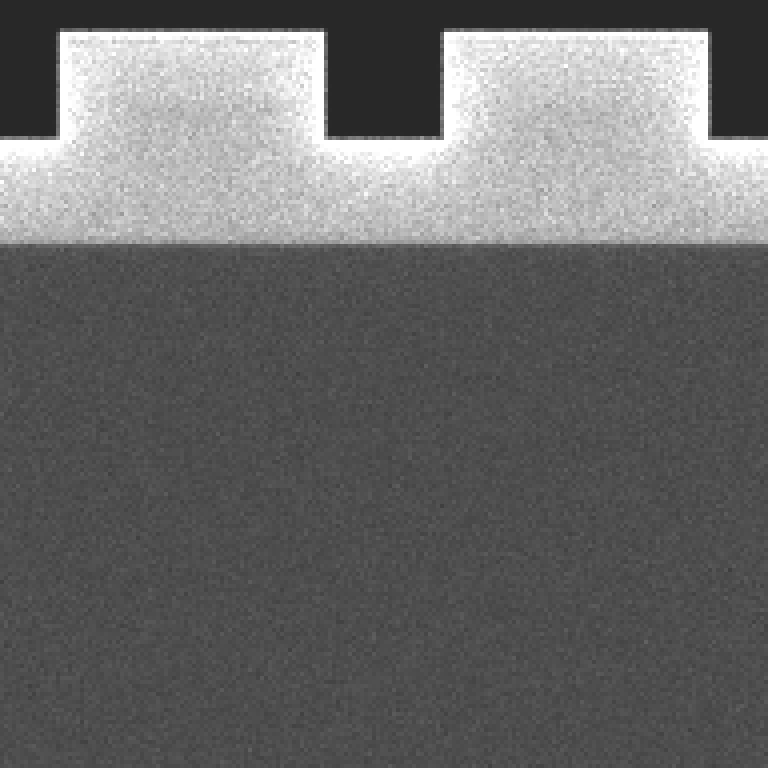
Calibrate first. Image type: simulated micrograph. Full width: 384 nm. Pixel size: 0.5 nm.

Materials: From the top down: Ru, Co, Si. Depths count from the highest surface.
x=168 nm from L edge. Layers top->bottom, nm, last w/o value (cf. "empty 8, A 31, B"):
empty 54, Co 52, Si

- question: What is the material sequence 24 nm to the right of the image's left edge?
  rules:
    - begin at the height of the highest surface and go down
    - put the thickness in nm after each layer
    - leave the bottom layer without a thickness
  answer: empty 54, Co 52, Si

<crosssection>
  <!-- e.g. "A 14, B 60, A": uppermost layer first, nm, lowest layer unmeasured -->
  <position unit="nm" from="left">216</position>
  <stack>empty 54, Co 52, Si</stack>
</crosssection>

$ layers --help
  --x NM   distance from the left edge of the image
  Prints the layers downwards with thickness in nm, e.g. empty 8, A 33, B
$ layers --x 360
empty 54, Co 52, Si